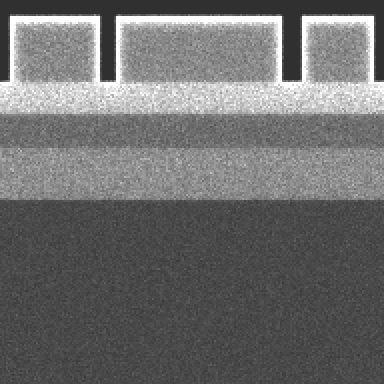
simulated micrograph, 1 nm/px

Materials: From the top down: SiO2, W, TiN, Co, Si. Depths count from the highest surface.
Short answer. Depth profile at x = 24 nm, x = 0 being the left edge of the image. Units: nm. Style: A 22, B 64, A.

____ SiO2 66, W 32, TiN 34, Co 52, Si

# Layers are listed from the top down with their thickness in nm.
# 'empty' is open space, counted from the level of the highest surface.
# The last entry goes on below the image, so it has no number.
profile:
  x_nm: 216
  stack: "SiO2 66, W 32, TiN 34, Co 52, Si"